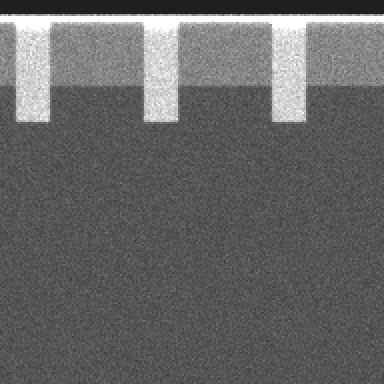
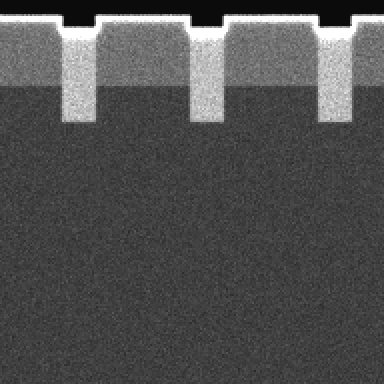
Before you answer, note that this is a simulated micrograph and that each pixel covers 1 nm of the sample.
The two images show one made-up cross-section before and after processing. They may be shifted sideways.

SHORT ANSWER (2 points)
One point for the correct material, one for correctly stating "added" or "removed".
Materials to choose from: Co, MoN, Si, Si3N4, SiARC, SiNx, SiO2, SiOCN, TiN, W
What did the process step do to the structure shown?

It removed SiO2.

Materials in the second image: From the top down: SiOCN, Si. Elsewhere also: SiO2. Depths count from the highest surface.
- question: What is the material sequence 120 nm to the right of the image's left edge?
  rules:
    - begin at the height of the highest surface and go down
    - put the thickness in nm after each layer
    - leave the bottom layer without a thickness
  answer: SiOCN 70, Si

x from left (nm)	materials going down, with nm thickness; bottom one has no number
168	SiOCN 70, Si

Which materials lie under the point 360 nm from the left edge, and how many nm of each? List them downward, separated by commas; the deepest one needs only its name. SiOCN 70, Si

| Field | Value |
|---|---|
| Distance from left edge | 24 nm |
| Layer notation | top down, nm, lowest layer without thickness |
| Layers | SiOCN 70, Si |